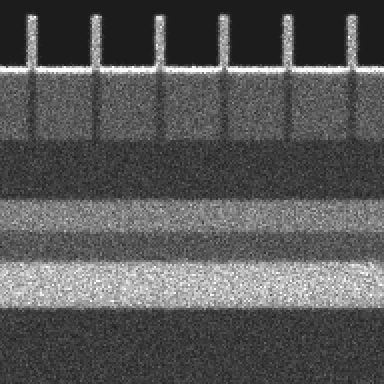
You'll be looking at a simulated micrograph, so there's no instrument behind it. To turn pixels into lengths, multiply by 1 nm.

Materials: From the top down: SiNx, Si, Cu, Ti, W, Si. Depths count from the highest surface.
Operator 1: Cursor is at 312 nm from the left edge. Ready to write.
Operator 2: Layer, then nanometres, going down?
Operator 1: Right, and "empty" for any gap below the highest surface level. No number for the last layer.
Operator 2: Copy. empty 52, SiNx 72, Si 60, Cu 32, Ti 30, W 46, Si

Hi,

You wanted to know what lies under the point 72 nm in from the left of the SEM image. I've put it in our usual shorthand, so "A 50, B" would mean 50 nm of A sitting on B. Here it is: empty 52, SiNx 72, Si 60, Cu 32, Ti 30, W 46, Si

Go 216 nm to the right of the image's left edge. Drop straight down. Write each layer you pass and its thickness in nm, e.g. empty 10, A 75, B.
empty 52, SiNx 72, Si 60, Cu 32, Ti 30, W 46, Si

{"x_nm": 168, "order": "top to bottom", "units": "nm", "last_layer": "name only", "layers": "empty 52, SiNx 72, Si 60, Cu 32, Ti 30, W 46, Si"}